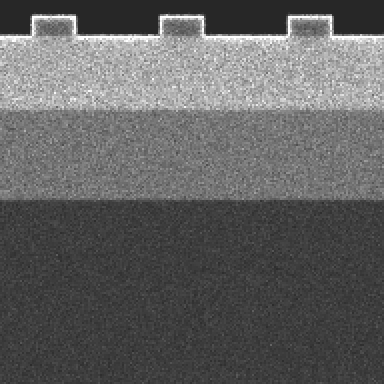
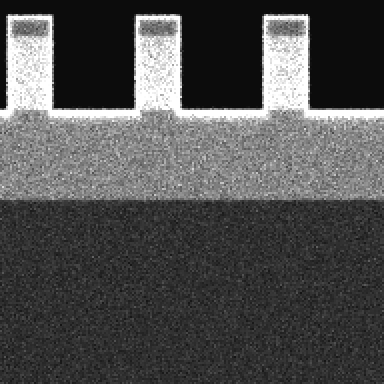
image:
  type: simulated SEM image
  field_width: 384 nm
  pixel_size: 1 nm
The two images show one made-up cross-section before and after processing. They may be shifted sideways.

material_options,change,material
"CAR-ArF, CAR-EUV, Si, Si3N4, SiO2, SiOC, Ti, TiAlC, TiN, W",removed,W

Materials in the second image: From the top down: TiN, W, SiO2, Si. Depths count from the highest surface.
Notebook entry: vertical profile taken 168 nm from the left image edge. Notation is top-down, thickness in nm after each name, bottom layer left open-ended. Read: TiN 20, W 74, SiO2 90, Si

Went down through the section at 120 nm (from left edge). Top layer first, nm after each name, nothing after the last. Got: empty 94, SiO2 90, Si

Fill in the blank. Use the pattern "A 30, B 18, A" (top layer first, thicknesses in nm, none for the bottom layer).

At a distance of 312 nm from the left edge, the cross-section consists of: empty 94, SiO2 90, Si